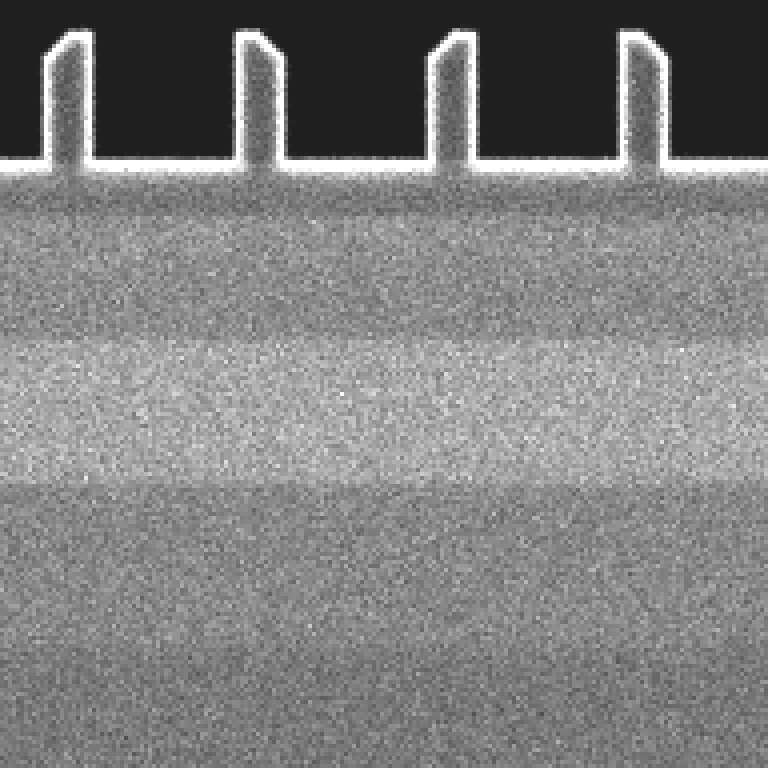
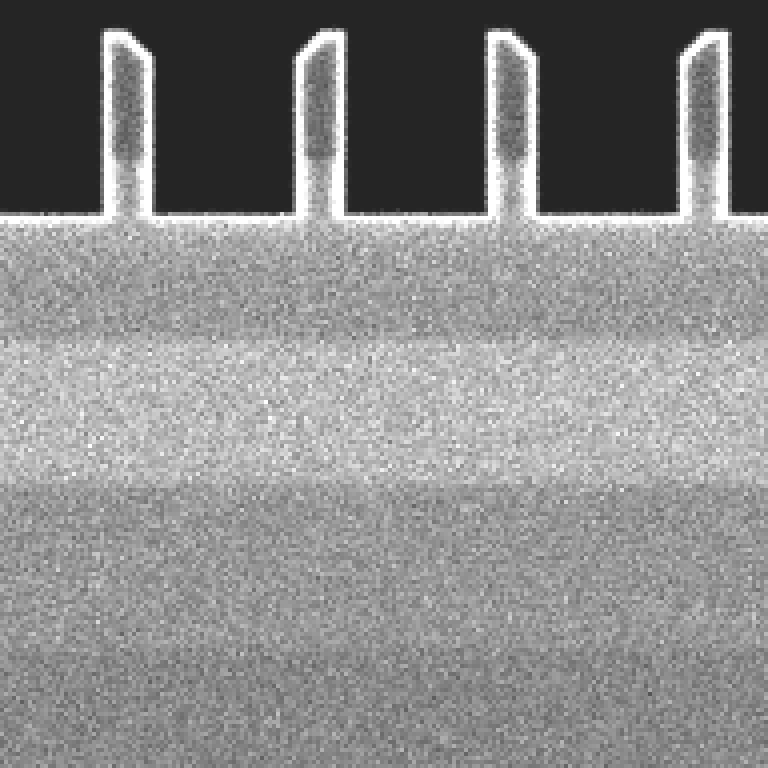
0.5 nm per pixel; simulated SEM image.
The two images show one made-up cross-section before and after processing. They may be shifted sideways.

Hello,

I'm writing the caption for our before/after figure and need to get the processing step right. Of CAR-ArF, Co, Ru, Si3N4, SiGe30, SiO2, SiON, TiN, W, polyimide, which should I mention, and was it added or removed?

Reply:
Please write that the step removed SiO2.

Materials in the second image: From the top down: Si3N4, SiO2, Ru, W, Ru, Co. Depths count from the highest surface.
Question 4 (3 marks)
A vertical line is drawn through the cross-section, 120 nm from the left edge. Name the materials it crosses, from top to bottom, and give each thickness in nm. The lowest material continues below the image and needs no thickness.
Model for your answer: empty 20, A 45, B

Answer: empty 92, Ru 62, W 72, Ru 82, Co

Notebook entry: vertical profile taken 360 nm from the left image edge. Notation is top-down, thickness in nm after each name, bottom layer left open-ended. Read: Si3N4 64, SiO2 28, Ru 62, W 72, Ru 82, Co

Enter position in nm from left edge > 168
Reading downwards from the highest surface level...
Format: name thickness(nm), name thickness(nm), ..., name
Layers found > Si3N4 64, SiO2 28, Ru 62, W 72, Ru 82, Co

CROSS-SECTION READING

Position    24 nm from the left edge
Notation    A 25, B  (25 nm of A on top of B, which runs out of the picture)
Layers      empty 92, Ru 62, W 72, Ru 82, Co